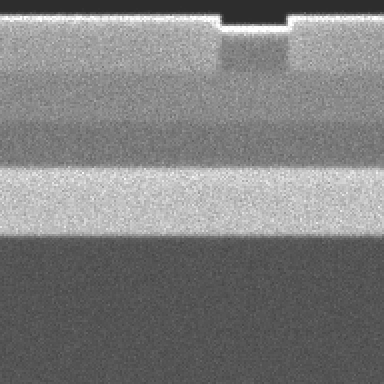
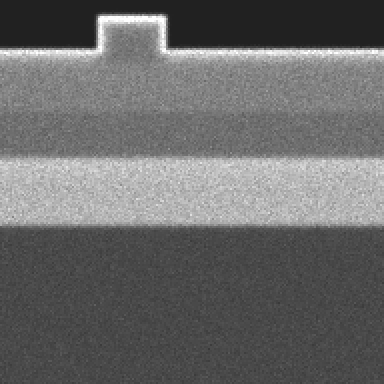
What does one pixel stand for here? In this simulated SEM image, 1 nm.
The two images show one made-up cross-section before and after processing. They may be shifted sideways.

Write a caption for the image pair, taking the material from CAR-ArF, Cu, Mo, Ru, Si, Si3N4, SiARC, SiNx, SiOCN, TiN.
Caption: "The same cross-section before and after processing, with TiN removed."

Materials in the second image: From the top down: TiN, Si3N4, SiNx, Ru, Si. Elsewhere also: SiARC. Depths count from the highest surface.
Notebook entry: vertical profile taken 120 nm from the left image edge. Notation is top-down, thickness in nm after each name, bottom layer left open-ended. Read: SiARC 46, Si3N4 50, SiNx 46, Ru 68, Si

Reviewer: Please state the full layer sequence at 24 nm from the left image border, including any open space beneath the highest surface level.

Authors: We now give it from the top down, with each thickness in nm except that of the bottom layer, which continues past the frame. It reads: empty 34, TiN 12, Si3N4 50, SiNx 46, Ru 68, Si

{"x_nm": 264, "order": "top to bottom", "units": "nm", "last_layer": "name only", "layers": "empty 34, TiN 12, Si3N4 50, SiNx 46, Ru 68, Si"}